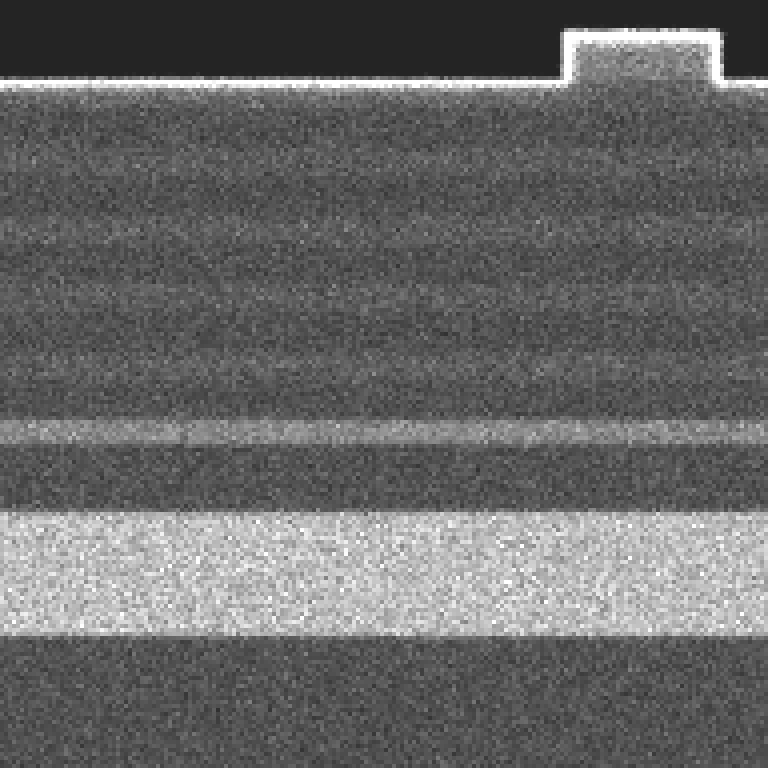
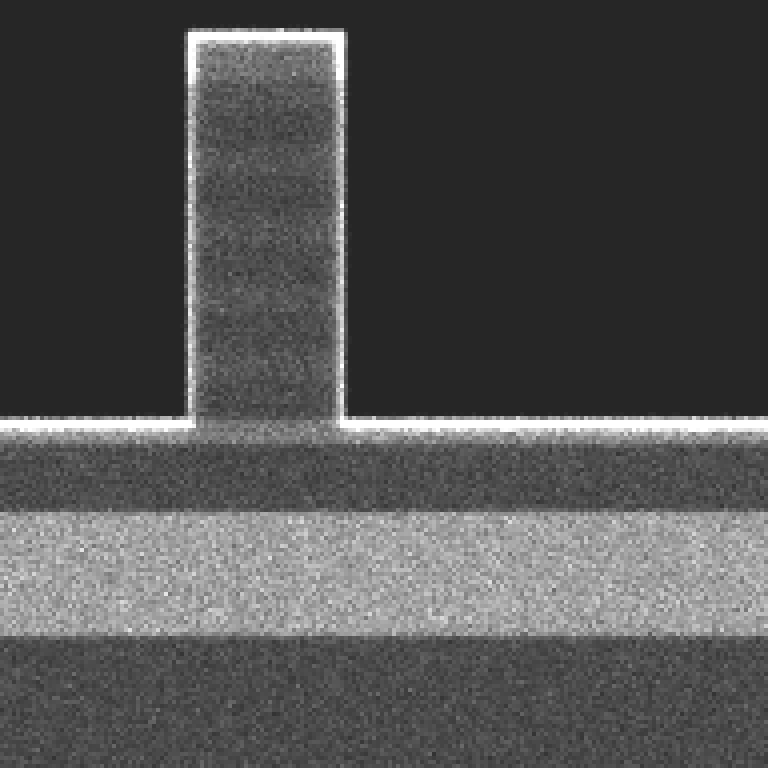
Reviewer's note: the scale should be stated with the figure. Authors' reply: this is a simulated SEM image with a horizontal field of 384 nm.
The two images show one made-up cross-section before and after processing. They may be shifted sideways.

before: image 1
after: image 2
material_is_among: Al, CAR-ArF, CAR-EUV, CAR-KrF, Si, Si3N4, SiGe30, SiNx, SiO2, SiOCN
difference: Si and SiGe30, removed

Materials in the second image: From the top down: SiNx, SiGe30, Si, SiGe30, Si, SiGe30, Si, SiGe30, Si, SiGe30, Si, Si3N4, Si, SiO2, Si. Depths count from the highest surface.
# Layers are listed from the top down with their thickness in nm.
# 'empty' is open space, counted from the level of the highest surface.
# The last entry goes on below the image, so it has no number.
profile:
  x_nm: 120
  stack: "SiNx 24, SiGe30 14, Si 20, SiGe30 14, Si 20, SiGe30 14, Si 20, SiGe30 14, Si 20, SiGe30 14, Si 20, Si3N4 12, Si 34, SiO2 62, Si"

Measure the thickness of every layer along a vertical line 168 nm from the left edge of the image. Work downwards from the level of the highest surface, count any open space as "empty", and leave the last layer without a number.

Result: SiNx 24, SiGe30 14, Si 20, SiGe30 14, Si 20, SiGe30 14, Si 20, SiGe30 14, Si 20, SiGe30 14, Si 20, Si3N4 12, Si 34, SiO2 62, Si